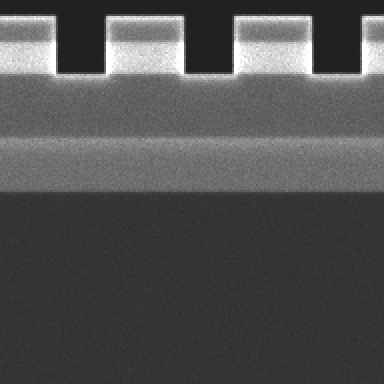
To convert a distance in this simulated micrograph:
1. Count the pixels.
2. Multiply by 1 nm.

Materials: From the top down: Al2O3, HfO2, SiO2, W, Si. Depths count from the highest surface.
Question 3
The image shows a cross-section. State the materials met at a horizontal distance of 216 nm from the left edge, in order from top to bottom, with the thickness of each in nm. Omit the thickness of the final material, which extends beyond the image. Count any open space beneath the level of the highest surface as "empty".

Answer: empty 58, SiO2 64, W 54, Si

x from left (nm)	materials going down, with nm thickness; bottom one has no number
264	Al2O3 26, HfO2 32, SiO2 64, W 54, Si